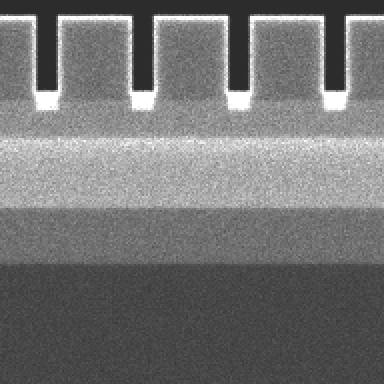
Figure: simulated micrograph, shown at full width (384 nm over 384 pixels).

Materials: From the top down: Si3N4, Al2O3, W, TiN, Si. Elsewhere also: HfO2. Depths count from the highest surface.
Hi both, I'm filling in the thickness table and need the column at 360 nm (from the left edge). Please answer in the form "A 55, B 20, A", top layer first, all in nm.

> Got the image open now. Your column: Si3N4 84, Al2O3 38, W 70, TiN 56, Si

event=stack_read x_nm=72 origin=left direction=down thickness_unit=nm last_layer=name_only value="Si3N4 84, Al2O3 38, W 70, TiN 56, Si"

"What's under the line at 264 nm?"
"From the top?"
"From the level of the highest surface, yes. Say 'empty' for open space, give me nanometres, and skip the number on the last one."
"Si3N4 84, Al2O3 38, W 70, TiN 56, Si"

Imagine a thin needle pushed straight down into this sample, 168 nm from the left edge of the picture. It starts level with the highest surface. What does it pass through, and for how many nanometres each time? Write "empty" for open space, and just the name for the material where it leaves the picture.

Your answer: Si3N4 84, Al2O3 38, W 70, TiN 56, Si